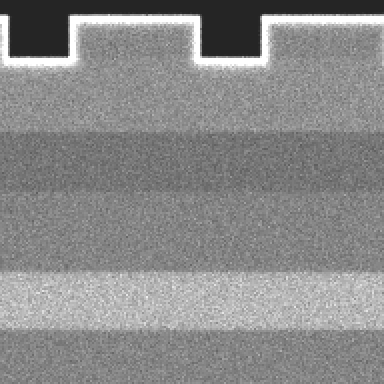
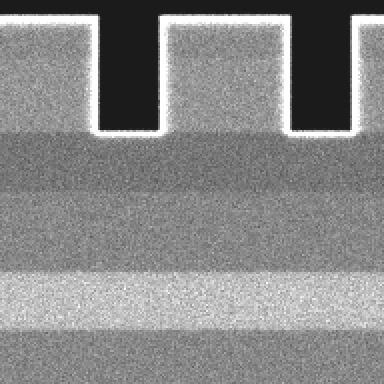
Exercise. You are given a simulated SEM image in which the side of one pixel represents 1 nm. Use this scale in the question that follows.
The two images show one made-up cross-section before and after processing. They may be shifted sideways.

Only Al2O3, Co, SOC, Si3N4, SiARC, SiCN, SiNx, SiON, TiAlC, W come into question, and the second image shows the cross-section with SOC removed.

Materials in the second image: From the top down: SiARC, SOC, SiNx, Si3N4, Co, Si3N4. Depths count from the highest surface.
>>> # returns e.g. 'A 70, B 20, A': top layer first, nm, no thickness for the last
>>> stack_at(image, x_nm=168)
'SiARC 42, SOC 74, SiNx 60, Si3N4 80, Co 58, Si3N4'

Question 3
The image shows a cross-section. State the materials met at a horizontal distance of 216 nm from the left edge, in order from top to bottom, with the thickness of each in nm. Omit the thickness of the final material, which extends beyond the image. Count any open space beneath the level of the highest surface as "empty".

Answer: SiARC 42, SOC 74, SiNx 60, Si3N4 80, Co 58, Si3N4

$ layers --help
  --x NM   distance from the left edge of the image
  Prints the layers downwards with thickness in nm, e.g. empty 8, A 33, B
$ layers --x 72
SiARC 42, SOC 74, SiNx 60, Si3N4 80, Co 58, Si3N4